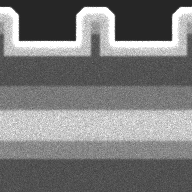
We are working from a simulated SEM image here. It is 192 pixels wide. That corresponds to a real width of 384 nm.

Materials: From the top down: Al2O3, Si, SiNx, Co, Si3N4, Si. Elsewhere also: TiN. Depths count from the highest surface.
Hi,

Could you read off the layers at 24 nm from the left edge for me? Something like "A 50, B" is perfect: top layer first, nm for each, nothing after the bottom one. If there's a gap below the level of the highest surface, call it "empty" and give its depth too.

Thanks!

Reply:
empty 4, Al2O3 92, Si 60, SiNx 48, Co 62, Si3N4 36, Si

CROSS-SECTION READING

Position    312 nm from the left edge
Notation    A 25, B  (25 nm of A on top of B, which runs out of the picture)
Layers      empty 68, Al2O3 28, Si 60, SiNx 48, Co 62, Si3N4 36, Si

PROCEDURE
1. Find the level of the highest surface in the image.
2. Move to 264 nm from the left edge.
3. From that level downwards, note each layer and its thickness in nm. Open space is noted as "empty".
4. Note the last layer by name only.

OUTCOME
empty 68, Al2O3 28, Si 60, SiNx 48, Co 62, Si3N4 36, Si